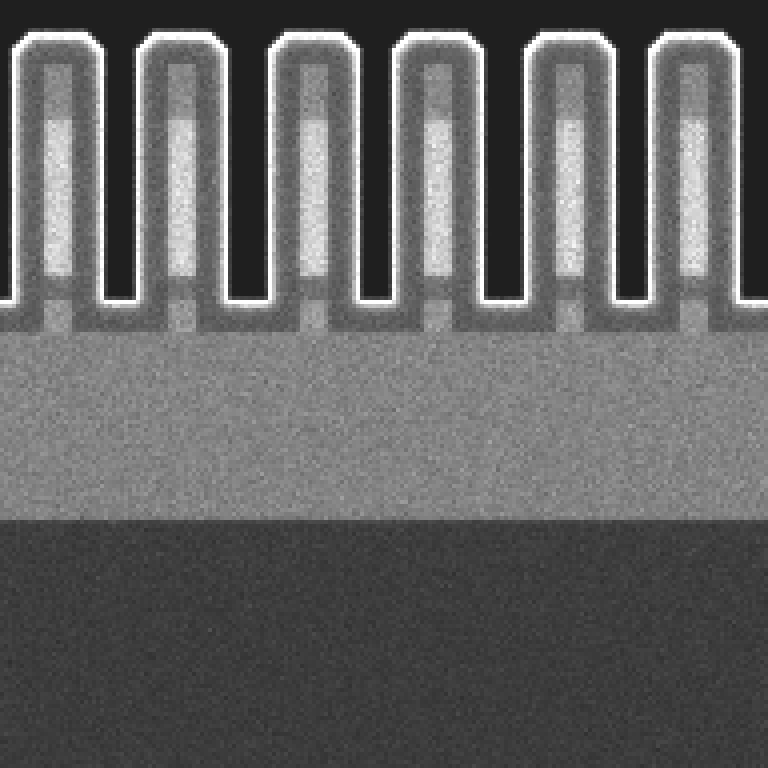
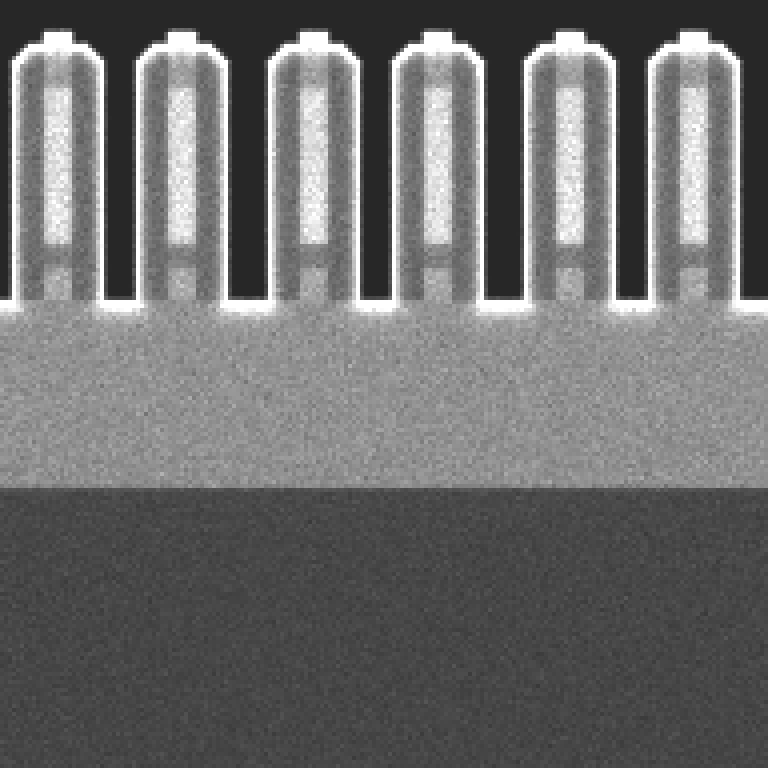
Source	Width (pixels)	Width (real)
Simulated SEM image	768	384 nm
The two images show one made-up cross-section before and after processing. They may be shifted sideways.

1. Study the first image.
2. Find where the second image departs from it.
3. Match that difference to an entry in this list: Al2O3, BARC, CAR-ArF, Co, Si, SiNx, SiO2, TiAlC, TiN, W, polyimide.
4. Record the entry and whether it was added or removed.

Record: SiNx / removed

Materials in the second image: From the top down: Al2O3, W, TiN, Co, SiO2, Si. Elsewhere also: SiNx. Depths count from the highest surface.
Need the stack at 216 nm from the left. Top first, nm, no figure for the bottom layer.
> Al2O3 28, W 78, TiN 12, Co 16, SiO2 94, Si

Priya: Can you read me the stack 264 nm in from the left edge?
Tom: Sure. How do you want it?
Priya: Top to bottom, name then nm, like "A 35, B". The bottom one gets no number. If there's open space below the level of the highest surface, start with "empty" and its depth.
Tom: empty 12, SiNx 122, SiO2 94, Si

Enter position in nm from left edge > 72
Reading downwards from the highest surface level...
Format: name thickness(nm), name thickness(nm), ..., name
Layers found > empty 10, SiNx 124, SiO2 94, Si